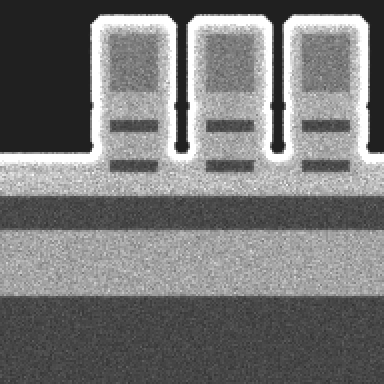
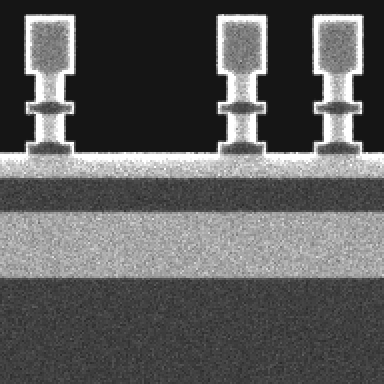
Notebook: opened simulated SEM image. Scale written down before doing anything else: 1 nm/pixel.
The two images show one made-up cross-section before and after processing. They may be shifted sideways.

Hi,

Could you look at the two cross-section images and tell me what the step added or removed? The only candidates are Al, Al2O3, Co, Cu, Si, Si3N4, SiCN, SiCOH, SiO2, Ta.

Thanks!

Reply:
removed Al2O3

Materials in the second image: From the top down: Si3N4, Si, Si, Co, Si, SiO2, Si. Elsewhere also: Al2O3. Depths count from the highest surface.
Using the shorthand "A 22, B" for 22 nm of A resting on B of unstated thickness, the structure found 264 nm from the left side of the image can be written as Si3N4 58, empty 28, Si 12, empty 28, Si 12, Co 24, Si 34, SiO2 66, Si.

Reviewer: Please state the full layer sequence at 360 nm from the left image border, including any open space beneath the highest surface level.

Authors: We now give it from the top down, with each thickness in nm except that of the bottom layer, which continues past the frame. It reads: Si3N4 58, empty 28, Si 12, empty 28, Si 12, Co 24, Si 34, SiO2 66, Si